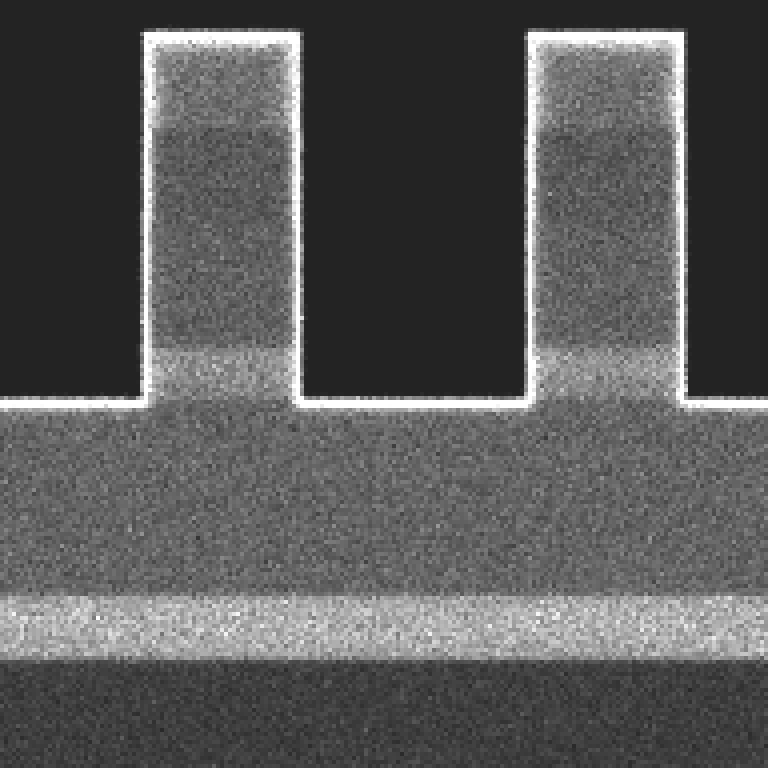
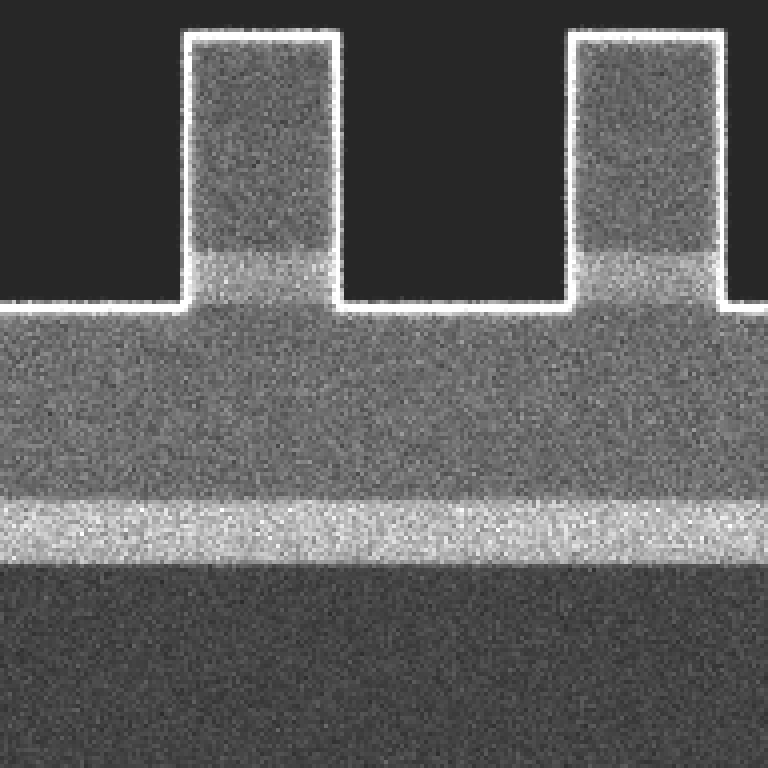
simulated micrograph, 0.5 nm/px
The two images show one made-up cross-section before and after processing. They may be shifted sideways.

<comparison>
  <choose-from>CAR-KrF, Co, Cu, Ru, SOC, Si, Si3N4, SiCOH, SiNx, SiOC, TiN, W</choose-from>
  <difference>SOC removed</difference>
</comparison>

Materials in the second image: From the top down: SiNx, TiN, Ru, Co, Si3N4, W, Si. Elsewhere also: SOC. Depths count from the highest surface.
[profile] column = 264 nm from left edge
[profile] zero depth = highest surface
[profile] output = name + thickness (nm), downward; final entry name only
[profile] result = empty 136, Si3N4 98, W 32, Si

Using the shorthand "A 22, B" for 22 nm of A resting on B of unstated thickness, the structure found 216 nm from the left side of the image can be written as empty 136, Si3N4 98, W 32, Si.